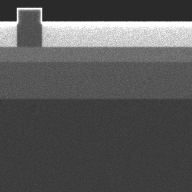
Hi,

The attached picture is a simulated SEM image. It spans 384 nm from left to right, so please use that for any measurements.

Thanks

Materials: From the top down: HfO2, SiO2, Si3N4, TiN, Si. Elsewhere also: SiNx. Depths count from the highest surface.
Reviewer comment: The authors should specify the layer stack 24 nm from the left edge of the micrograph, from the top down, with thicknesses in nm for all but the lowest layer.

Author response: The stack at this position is empty 28, HfO2 50, SiO2 30, Si3N4 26, TiN 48, Si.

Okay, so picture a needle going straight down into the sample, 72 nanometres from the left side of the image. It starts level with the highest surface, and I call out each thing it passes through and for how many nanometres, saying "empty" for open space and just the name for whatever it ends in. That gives SiNx 78, SiO2 30, Si3N4 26, TiN 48, Si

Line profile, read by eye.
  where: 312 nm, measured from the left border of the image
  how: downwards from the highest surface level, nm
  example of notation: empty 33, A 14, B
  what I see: empty 28, HfO2 50, SiO2 30, Si3N4 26, TiN 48, Si